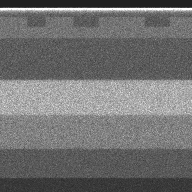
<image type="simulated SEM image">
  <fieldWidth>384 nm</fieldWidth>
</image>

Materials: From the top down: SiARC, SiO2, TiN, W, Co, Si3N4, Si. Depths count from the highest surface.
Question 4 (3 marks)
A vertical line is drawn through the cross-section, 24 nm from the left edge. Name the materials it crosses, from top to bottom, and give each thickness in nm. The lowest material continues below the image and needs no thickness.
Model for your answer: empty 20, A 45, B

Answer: SiARC 18, SiO2 42, TiN 84, W 70, Co 68, Si3N4 58, Si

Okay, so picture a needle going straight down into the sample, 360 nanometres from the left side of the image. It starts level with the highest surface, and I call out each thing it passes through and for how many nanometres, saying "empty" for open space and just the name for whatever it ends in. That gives SiARC 18, SiO2 42, TiN 84, W 70, Co 68, Si3N4 58, Si